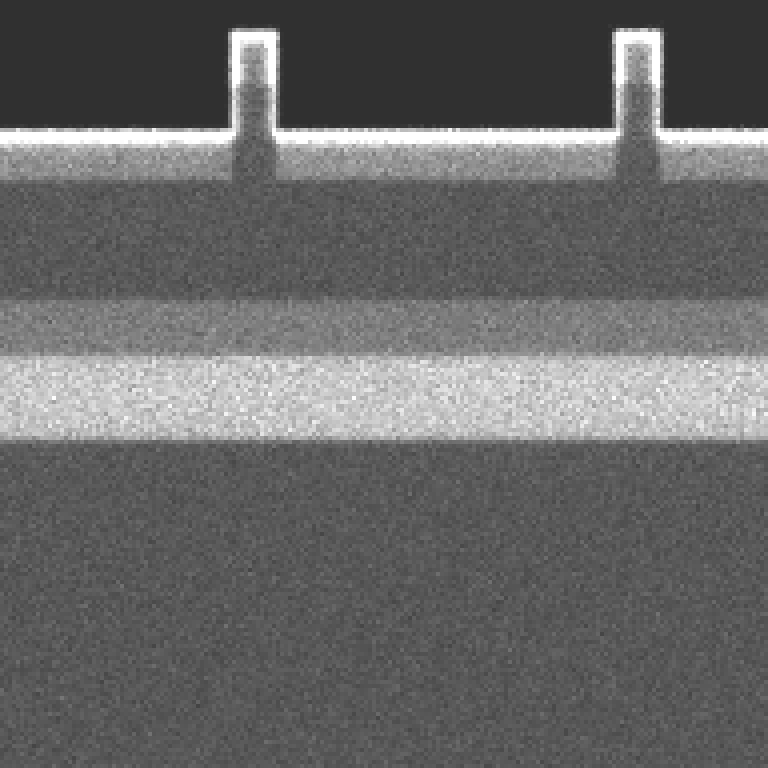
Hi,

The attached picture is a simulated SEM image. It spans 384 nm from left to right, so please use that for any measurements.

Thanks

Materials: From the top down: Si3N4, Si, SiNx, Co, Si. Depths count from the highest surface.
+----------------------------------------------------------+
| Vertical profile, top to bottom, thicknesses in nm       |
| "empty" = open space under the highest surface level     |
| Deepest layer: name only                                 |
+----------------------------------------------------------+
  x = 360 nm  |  empty 50, Si3N4 24, Si 60, SiNx 28, Co 42, Si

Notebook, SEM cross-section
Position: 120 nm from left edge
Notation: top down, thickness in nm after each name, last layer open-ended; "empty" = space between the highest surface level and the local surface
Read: SiNx 26, Si 108, SiNx 28, Co 42, Si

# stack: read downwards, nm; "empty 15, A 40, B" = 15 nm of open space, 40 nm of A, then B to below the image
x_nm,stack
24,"empty 50, Si3N4 24, Si 60, SiNx 28, Co 42, Si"